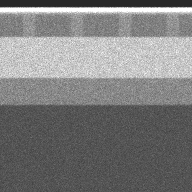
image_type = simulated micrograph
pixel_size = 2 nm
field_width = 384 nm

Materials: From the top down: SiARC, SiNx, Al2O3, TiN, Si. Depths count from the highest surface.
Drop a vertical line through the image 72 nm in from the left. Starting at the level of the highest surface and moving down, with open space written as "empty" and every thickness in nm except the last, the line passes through SiARC 10, SiNx 48, Al2O3 82, TiN 54, Si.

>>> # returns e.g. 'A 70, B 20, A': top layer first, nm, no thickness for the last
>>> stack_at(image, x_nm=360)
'SiARC 10, SiNx 48, Al2O3 82, TiN 54, Si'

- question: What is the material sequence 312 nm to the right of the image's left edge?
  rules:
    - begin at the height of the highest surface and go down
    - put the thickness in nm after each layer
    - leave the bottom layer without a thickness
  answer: SiARC 10, SiNx 48, Al2O3 82, TiN 54, Si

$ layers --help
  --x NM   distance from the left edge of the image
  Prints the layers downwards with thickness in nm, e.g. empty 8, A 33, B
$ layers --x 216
SiARC 10, SiNx 48, Al2O3 82, TiN 54, Si